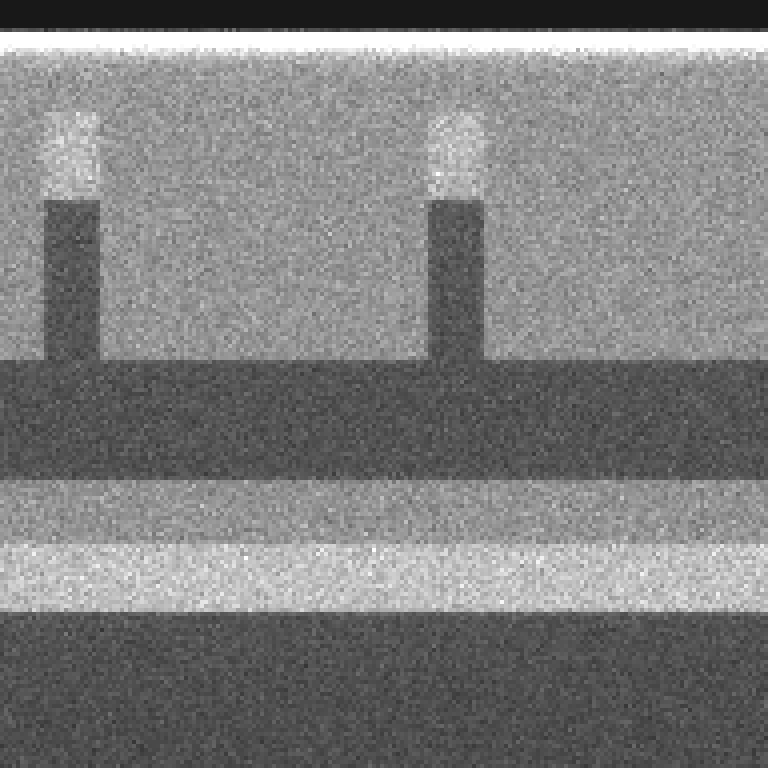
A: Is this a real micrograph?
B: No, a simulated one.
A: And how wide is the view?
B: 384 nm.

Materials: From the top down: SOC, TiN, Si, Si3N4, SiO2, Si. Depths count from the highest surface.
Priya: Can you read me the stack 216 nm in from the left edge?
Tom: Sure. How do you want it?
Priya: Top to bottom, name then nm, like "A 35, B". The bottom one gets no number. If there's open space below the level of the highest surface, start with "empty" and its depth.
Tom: SOC 40, TiN 44, Si 140, Si3N4 32, SiO2 34, Si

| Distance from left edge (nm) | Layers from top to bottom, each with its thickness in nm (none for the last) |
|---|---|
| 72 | SOC 164, Si 60, Si3N4 32, SiO2 34, Si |